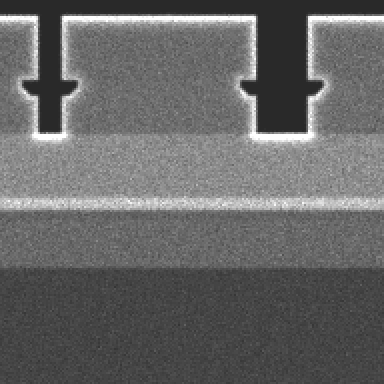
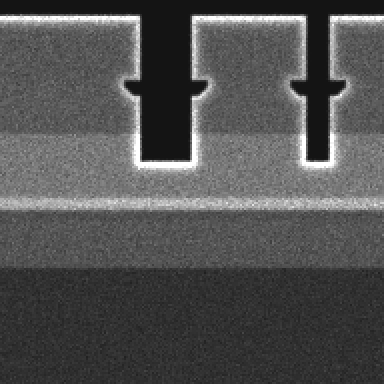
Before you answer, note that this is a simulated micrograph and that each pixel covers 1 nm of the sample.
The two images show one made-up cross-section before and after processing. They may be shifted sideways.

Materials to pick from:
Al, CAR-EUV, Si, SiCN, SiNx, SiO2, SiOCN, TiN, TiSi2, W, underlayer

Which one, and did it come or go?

SiO2 - removed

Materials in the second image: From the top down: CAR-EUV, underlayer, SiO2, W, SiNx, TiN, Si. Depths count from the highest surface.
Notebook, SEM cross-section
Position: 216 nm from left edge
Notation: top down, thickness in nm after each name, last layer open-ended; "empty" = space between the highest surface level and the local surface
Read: CAR-EUV 64, underlayer 54, SiO2 64, W 12, SiNx 10, TiN 48, Si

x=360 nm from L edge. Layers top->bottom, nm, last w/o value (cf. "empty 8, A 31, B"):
CAR-EUV 64, underlayer 54, SiO2 64, W 12, SiNx 10, TiN 48, Si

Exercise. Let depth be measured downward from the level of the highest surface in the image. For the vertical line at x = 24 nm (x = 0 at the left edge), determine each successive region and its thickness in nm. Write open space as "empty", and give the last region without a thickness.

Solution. CAR-EUV 64, underlayer 54, SiO2 64, W 12, SiNx 10, TiN 48, Si